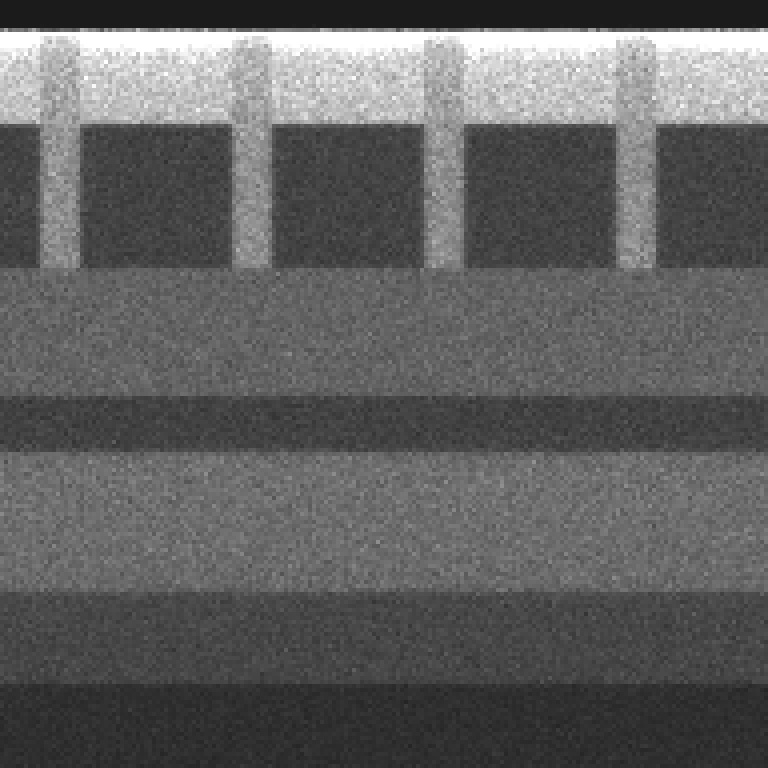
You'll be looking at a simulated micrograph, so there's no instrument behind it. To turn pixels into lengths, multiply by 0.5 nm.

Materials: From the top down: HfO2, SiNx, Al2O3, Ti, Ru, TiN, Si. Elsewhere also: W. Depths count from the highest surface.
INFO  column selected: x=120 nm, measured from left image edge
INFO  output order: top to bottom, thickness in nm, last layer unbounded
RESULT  W 118, Al2O3 64, Ti 28, Ru 70, TiN 46, Si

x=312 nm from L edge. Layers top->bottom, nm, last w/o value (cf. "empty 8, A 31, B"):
W 118, Al2O3 64, Ti 28, Ru 70, TiN 46, Si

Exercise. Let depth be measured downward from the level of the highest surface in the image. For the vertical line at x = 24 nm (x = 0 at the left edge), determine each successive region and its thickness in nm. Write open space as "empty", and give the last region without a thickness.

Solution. W 118, Al2O3 64, Ti 28, Ru 70, TiN 46, Si